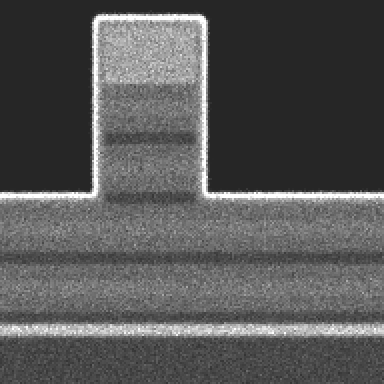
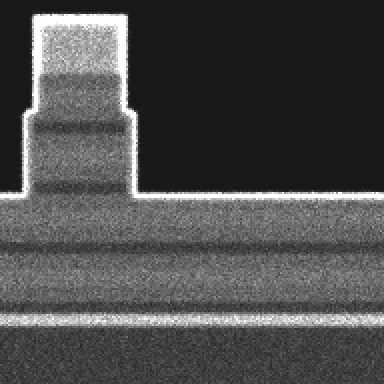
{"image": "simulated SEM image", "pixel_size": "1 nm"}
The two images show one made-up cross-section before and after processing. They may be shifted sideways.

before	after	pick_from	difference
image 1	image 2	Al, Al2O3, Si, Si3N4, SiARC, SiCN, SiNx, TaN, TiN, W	TiN removed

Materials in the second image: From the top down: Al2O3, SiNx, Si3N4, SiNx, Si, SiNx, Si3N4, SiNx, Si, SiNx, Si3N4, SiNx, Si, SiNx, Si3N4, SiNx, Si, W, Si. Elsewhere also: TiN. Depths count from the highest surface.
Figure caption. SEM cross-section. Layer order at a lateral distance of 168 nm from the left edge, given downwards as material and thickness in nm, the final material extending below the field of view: empty 178, SiNx 16, Si3N4 16, SiNx 16, Si 12, SiNx 16, Si3N4 16, SiNx 16, Si 12, W 12, Si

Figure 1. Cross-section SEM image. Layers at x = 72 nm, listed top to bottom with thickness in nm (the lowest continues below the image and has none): Al2O3 58, SiNx 16, Si3N4 16, SiNx 16, Si 12, SiNx 16, Si3N4 16, SiNx 16, Si 12, SiNx 16, Si3N4 16, SiNx 16, Si 12, SiNx 16, Si3N4 16, SiNx 16, Si 12, W 12, Si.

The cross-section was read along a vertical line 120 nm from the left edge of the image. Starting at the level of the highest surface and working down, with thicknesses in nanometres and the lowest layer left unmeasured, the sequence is Al2O3 58, SiNx 16, Si3N4 16, SiNx 16, Si 12, SiNx 16, Si3N4 16, SiNx 16, Si 12, SiNx 16, Si3N4 16, SiNx 16, Si 12, SiNx 16, Si3N4 16, SiNx 16, Si 12, W 12, Si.